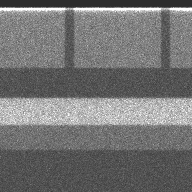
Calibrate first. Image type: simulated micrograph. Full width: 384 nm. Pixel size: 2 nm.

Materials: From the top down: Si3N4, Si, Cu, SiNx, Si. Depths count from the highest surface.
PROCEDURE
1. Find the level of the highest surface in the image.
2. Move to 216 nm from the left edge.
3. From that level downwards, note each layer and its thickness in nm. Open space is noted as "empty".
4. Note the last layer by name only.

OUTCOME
Si3N4 120, Si 60, Cu 54, SiNx 50, Si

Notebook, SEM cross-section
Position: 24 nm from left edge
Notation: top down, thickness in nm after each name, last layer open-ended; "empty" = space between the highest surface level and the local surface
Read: Si3N4 120, Si 60, Cu 54, SiNx 50, Si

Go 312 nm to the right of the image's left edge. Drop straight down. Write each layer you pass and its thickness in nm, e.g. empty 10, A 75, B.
Si3N4 120, Si 60, Cu 54, SiNx 50, Si